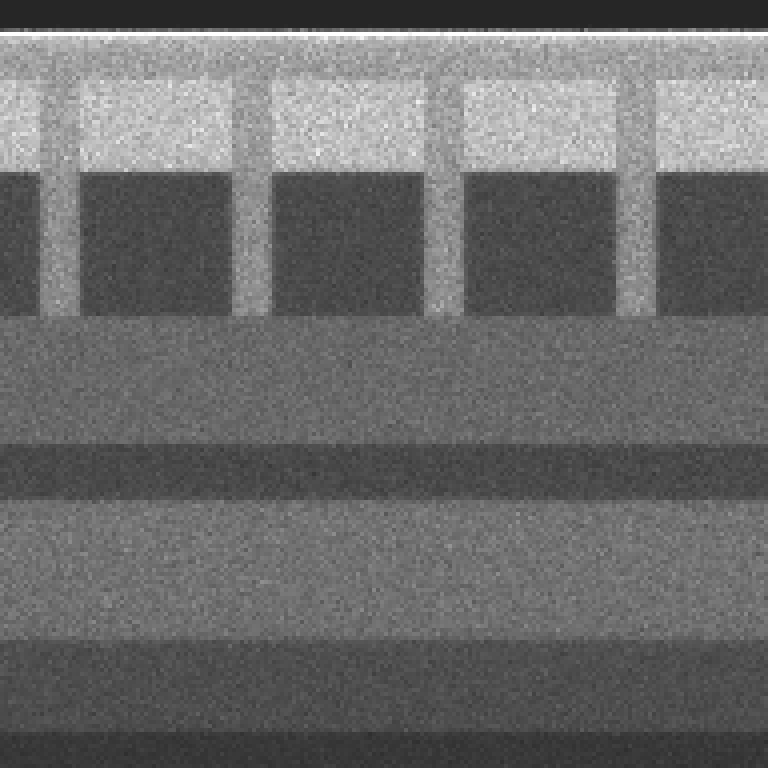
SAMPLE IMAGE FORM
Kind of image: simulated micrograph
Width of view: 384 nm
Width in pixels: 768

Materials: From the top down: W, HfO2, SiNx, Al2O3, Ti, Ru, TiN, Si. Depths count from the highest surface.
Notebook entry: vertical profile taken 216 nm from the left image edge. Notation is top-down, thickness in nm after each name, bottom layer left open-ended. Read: W 142, Al2O3 64, Ti 28, Ru 70, TiN 46, Si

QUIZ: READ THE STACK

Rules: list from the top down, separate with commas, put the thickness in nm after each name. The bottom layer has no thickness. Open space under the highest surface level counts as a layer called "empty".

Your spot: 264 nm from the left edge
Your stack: W 24, HfO2 46, SiNx 72, Al2O3 64, Ti 28, Ru 70, TiN 46, Si